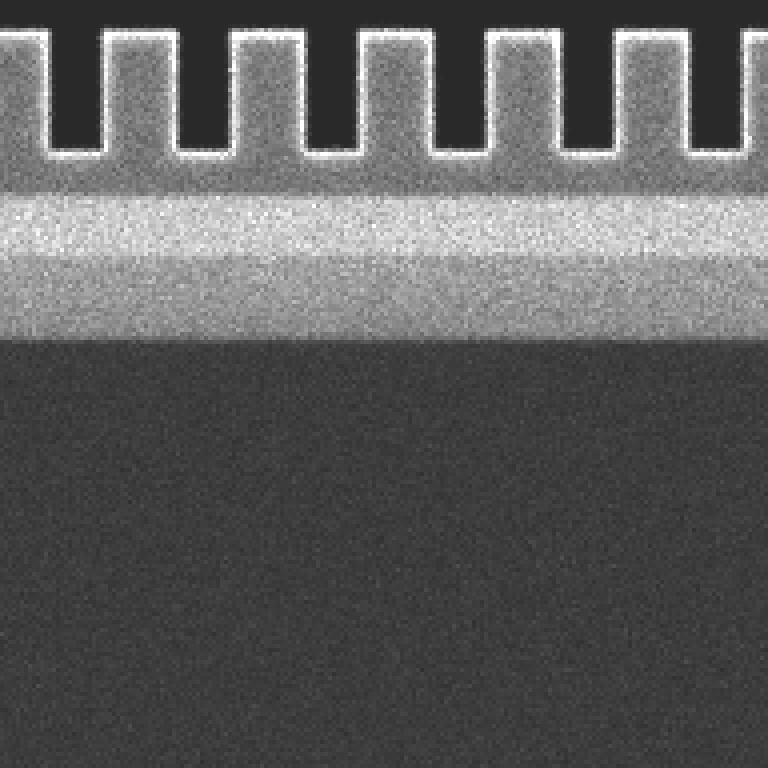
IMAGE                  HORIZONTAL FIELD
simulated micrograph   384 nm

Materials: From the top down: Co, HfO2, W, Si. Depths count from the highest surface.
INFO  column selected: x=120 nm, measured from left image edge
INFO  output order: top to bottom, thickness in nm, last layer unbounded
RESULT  Co 82, HfO2 30, W 42, Si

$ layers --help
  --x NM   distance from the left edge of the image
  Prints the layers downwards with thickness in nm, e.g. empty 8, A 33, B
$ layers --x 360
empty 60, Co 22, HfO2 30, W 42, Si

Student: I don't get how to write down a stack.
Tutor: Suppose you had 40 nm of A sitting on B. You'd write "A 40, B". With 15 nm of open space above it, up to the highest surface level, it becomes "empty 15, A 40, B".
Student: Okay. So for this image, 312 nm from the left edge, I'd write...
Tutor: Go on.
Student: Co 82, HfO2 30, W 42, Si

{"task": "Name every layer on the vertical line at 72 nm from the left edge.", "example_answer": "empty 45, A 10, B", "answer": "Co 82, HfO2 30, W 42, Si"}